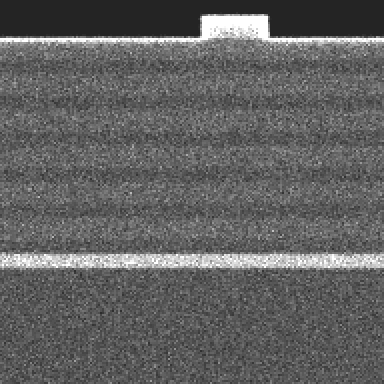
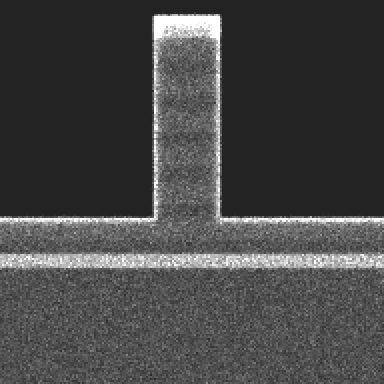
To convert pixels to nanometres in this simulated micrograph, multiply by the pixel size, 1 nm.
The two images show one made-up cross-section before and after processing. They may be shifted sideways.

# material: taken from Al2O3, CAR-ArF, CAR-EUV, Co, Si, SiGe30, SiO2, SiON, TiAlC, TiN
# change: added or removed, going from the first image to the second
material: Si and SiGe30
change: removed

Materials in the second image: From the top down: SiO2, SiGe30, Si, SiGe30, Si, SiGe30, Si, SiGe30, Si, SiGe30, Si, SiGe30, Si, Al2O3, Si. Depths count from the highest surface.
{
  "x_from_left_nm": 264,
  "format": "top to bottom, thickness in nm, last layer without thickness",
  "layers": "empty 202, SiGe30 22, Si 14, Al2O3 14, Si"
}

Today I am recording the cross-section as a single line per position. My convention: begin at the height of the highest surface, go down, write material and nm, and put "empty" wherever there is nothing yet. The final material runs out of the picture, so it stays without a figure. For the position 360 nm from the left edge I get empty 202, SiGe30 22, Si 14, Al2O3 14, Si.